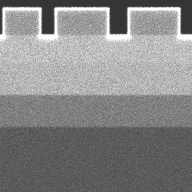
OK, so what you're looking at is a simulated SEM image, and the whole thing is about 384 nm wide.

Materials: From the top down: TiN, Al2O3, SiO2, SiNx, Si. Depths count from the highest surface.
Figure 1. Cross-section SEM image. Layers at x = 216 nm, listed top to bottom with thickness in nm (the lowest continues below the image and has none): TiN 54, Al2O3 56, SiO2 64, SiNx 64, Si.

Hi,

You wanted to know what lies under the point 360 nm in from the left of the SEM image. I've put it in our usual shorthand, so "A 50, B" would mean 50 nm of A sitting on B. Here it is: empty 54, Al2O3 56, SiO2 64, SiNx 64, Si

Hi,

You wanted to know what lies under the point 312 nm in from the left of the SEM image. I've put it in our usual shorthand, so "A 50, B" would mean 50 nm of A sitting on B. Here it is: TiN 54, Al2O3 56, SiO2 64, SiNx 64, Si